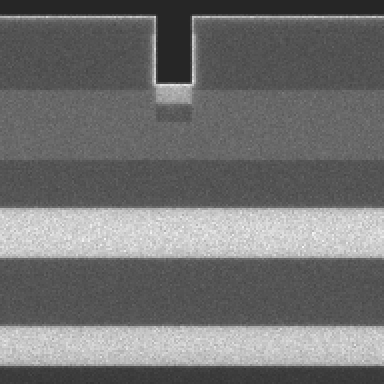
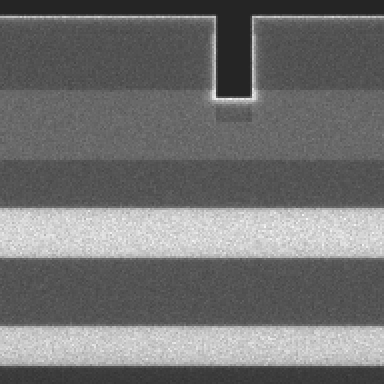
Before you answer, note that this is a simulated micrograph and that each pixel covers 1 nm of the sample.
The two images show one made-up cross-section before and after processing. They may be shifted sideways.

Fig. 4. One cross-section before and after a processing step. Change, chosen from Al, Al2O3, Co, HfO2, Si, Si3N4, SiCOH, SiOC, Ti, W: W removed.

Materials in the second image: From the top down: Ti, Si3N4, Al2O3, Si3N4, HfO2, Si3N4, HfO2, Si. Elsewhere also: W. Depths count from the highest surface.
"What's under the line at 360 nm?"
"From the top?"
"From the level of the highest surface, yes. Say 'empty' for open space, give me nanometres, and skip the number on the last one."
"Ti 18, Si3N4 56, Al2O3 70, Si3N4 48, HfO2 50, Si3N4 68, HfO2 40, Si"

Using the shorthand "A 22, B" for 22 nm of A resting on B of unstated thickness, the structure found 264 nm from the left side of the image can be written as Ti 18, Si3N4 56, Al2O3 70, Si3N4 48, HfO2 50, Si3N4 68, HfO2 40, Si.